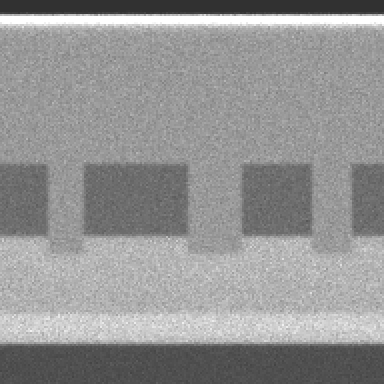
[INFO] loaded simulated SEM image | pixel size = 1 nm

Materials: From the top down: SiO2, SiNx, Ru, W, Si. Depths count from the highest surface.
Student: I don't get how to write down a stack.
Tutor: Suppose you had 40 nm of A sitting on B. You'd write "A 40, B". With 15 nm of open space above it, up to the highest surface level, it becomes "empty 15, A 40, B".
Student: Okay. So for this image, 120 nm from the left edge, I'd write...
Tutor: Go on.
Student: SiO2 148, SiNx 72, Ru 78, W 30, Si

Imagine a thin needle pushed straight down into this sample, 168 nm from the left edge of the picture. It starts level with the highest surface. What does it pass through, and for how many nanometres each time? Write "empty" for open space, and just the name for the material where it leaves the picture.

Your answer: SiO2 148, SiNx 72, Ru 78, W 30, Si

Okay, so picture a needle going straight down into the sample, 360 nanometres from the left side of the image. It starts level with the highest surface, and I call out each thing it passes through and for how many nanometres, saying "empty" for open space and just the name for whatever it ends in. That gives SiO2 148, SiNx 72, Ru 78, W 30, Si